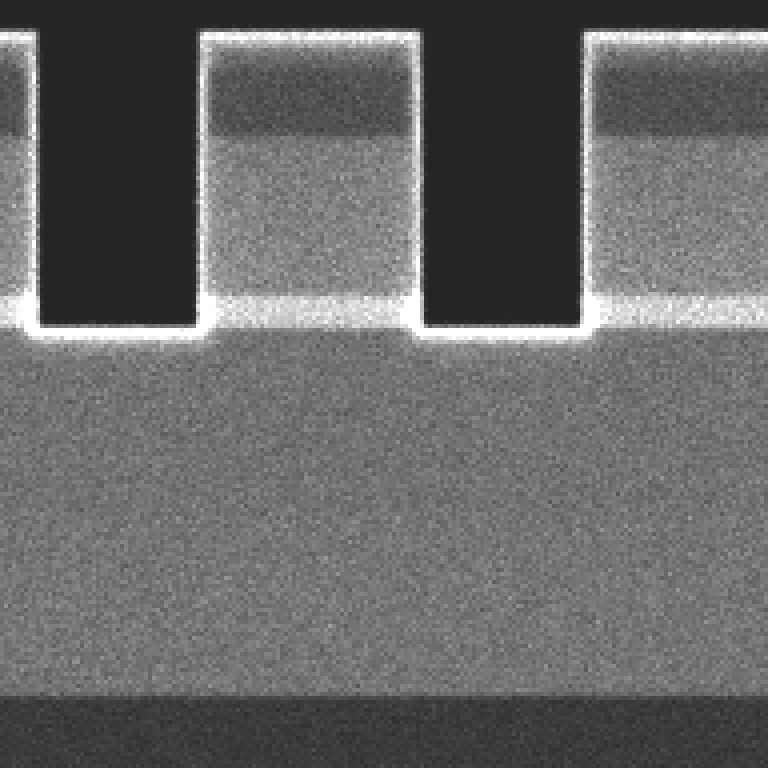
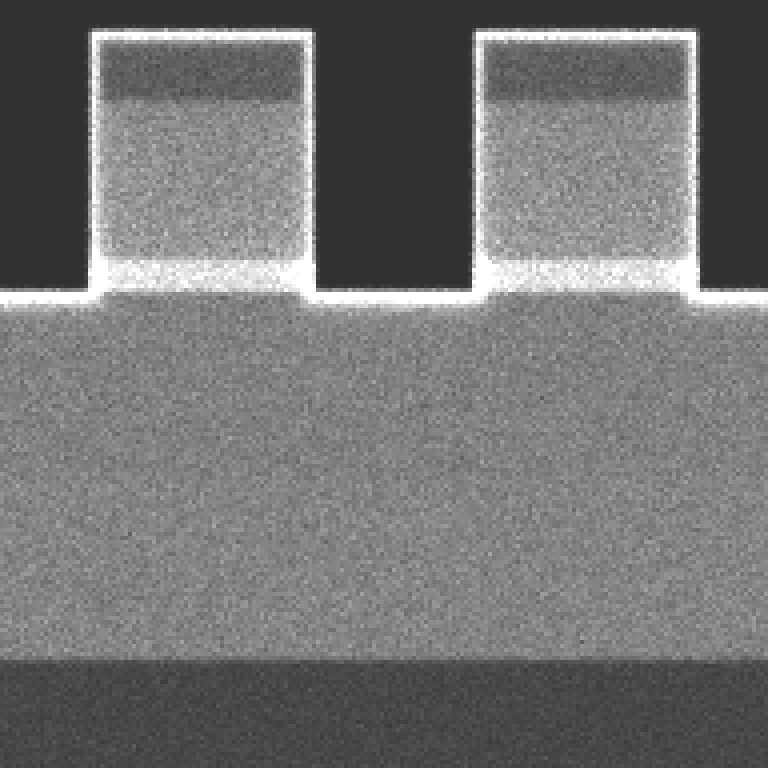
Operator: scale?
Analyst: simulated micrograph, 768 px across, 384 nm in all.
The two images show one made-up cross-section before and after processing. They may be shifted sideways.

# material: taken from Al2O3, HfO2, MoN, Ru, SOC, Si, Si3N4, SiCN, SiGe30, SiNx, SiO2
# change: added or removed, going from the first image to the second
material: SOC
change: removed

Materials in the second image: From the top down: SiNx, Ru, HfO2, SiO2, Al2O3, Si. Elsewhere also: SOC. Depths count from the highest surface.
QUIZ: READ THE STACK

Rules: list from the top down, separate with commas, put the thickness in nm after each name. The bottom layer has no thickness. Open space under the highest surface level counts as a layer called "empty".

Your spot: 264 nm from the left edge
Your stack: SiNx 34, Ru 80, HfO2 16, SiO2 94, Al2O3 90, Si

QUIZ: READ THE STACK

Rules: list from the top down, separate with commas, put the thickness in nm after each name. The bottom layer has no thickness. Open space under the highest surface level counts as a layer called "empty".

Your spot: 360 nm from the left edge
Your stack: empty 130, SiO2 94, Al2O3 90, Si